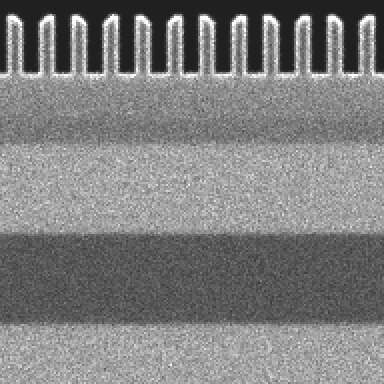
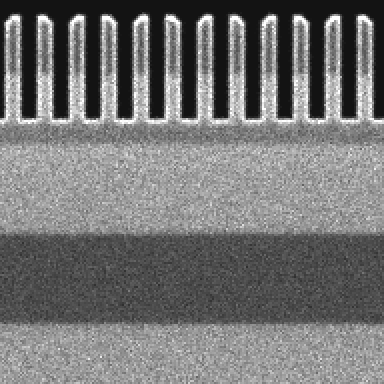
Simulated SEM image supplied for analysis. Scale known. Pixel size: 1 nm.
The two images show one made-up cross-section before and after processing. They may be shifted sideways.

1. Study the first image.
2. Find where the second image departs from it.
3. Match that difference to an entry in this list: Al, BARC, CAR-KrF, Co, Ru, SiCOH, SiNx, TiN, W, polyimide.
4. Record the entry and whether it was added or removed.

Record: Ru / removed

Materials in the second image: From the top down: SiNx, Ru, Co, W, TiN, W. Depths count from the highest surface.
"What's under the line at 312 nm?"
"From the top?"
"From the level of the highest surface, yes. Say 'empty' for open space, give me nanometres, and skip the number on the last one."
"empty 104, Co 24, W 90, TiN 90, W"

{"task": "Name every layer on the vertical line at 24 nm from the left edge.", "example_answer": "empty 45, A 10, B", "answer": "empty 104, Co 24, W 90, TiN 90, W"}